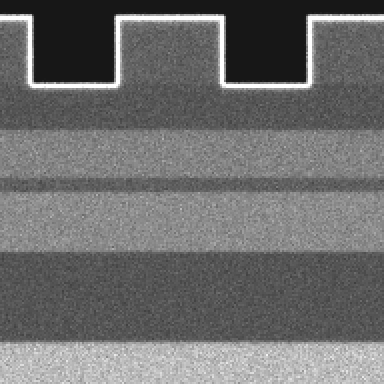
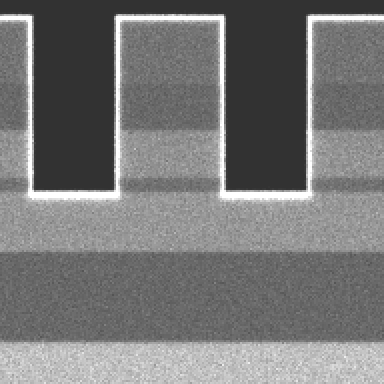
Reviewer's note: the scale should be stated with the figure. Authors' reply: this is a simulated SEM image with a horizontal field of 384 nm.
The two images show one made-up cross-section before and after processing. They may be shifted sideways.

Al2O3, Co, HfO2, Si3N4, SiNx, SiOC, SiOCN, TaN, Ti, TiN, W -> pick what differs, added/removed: Co and SiNx and TiN removed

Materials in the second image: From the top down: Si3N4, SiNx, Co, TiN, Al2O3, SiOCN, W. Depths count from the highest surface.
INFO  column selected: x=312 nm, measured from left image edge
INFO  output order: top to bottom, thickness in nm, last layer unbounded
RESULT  Si3N4 68, SiNx 46, Co 48, TiN 14, Al2O3 60, SiOCN 90, W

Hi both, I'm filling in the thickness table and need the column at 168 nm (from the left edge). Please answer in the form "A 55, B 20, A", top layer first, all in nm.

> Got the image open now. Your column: Si3N4 68, SiNx 46, Co 48, TiN 14, Al2O3 60, SiOCN 90, W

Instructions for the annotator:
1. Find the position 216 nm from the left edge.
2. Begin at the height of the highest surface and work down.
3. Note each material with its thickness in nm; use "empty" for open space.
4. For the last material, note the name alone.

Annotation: Si3N4 68, SiNx 46, Co 48, TiN 14, Al2O3 60, SiOCN 90, W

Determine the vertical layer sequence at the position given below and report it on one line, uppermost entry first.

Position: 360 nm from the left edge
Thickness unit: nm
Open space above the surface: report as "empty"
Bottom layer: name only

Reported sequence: Si3N4 68, SiNx 46, Co 48, TiN 14, Al2O3 60, SiOCN 90, W